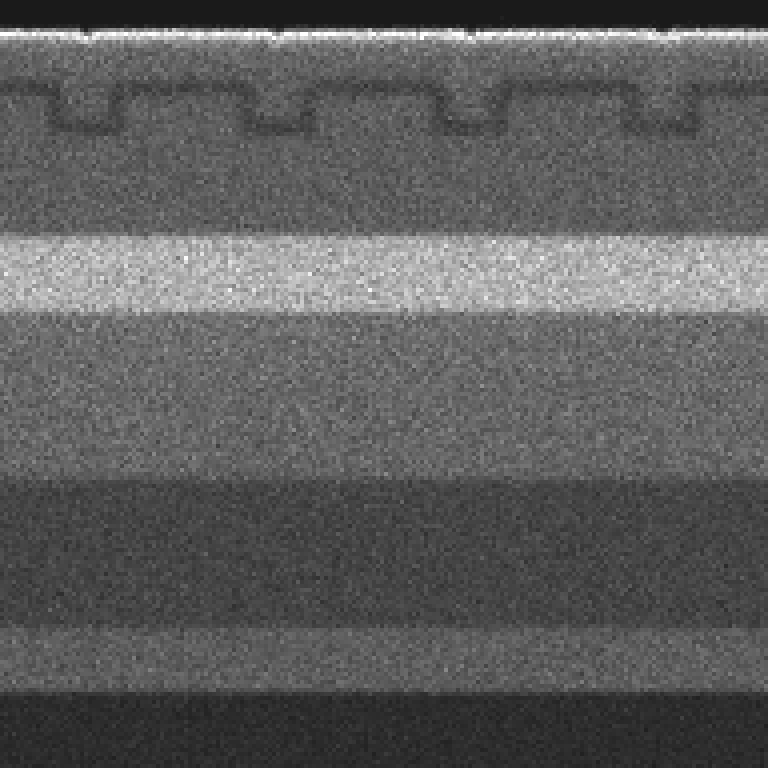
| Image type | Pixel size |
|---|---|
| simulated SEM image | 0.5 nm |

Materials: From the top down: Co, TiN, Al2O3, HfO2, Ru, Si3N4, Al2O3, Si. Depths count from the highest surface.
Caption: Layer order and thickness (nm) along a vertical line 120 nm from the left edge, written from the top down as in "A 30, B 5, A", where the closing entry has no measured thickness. Co 24, TiN 28, Al2O3 50, HfO2 38, Ru 84, Si3N4 74, Al2O3 32, Si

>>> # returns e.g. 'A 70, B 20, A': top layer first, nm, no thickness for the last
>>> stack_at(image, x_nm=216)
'Co 24, TiN 28, Al2O3 50, HfO2 38, Ru 84, Si3N4 74, Al2O3 32, Si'